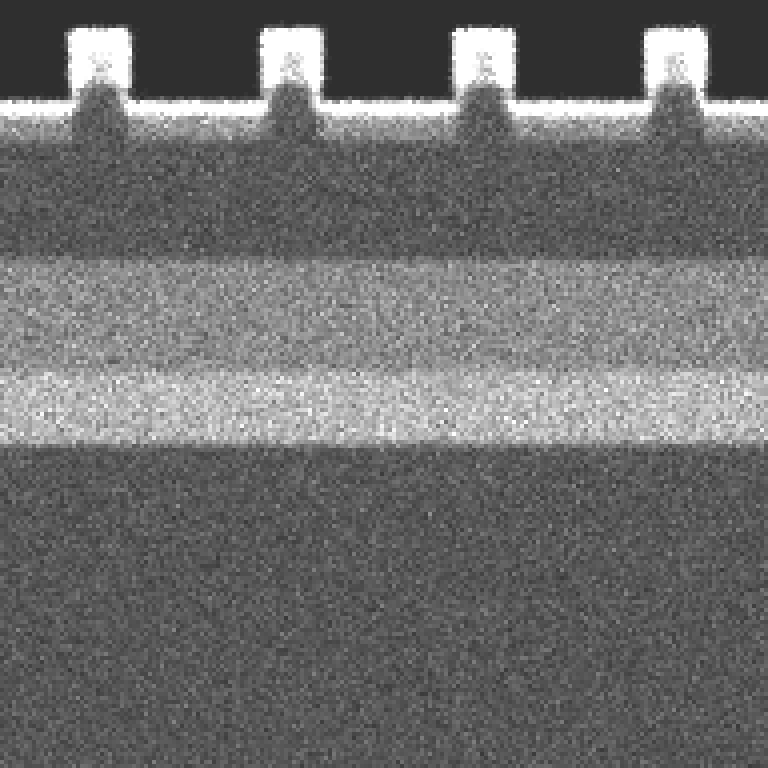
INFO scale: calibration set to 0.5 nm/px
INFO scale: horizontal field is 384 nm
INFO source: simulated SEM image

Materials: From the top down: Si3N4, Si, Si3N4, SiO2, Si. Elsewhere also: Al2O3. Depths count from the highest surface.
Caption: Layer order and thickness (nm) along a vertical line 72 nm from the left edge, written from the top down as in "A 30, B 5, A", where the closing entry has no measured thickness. empty 36, Si3N4 18, Si 60, Si3N4 56, SiO2 36, Si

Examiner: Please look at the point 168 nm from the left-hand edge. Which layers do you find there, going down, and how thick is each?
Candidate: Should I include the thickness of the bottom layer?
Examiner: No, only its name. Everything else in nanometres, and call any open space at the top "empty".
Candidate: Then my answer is empty 36, Si3N4 18, Si 60, Si3N4 56, SiO2 36, Si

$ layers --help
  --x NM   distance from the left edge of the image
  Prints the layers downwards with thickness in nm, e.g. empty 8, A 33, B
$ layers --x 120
empty 36, Si3N4 18, Si 60, Si3N4 56, SiO2 36, Si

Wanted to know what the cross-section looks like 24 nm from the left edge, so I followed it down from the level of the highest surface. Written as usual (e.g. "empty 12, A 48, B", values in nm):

empty 36, Si3N4 18, Si 60, Si3N4 56, SiO2 36, Si